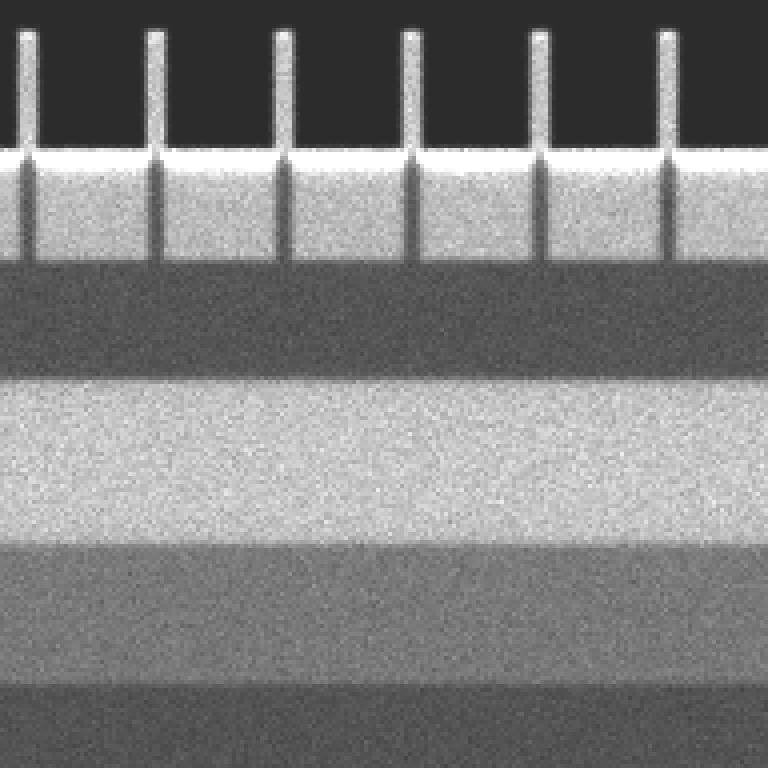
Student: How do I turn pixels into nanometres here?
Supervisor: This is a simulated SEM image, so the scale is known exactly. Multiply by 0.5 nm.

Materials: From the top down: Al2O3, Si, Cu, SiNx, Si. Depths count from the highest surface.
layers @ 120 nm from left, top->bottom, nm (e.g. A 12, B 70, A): empty 60, Al2O3 54, Si 60, Cu 82, SiNx 70, Si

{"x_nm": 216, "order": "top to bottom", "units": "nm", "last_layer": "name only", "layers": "empty 60, Al2O3 54, Si 60, Cu 82, SiNx 70, Si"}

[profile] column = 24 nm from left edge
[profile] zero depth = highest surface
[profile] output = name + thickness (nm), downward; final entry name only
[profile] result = empty 60, Al2O3 54, Si 60, Cu 82, SiNx 70, Si